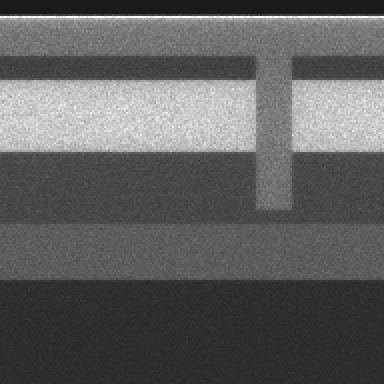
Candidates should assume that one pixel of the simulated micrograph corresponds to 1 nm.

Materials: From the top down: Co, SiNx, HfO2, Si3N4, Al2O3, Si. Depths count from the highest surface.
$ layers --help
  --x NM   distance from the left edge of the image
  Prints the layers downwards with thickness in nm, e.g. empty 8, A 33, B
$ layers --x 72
Co 40, SiNx 24, HfO2 72, Si3N4 72, Al2O3 56, Si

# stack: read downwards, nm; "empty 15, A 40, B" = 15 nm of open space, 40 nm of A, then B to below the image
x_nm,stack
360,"Co 40, SiNx 24, HfO2 72, Si3N4 72, Al2O3 56, Si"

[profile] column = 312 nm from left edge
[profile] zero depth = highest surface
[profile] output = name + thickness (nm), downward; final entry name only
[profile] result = Co 40, SiNx 24, HfO2 72, Si3N4 72, Al2O3 56, Si